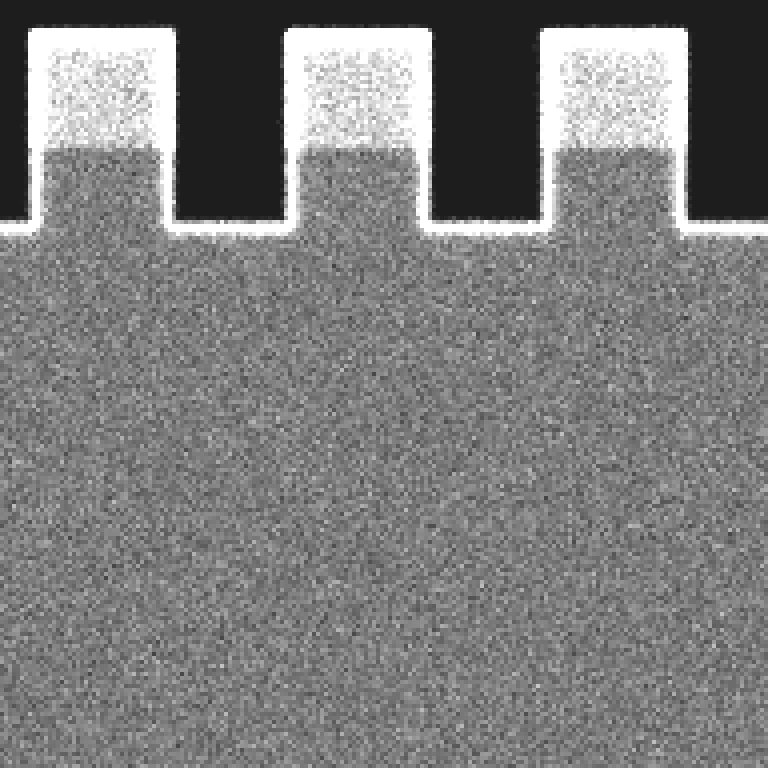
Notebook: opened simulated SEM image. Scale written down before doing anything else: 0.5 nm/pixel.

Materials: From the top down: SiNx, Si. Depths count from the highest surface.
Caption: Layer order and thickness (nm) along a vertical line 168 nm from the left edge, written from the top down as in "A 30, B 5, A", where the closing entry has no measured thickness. SiNx 58, Si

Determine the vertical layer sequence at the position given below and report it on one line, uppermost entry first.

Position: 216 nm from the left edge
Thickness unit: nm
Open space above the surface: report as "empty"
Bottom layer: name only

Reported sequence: empty 96, Si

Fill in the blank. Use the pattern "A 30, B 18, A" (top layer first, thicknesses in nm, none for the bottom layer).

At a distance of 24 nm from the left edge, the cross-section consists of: SiNx 58, Si